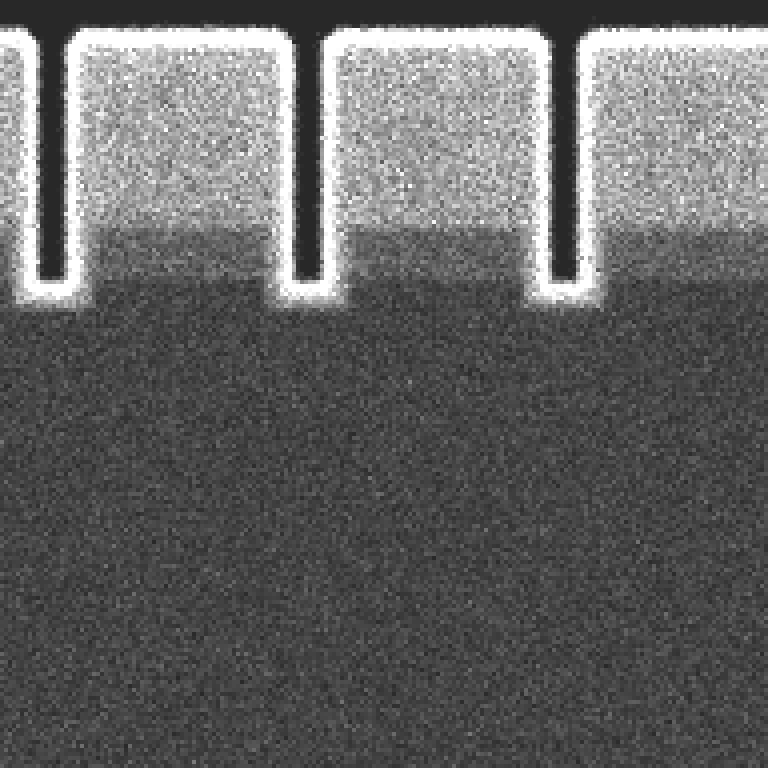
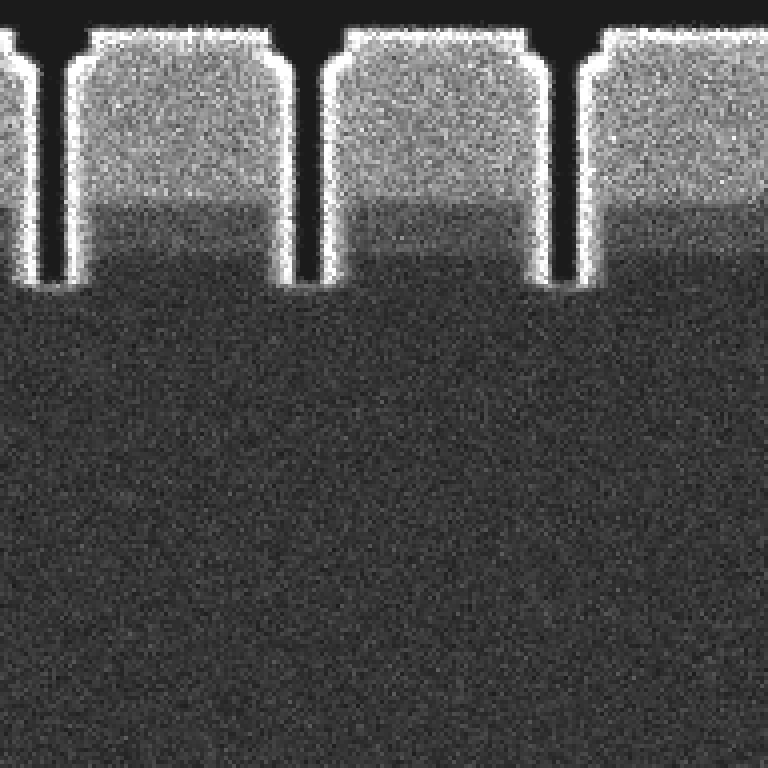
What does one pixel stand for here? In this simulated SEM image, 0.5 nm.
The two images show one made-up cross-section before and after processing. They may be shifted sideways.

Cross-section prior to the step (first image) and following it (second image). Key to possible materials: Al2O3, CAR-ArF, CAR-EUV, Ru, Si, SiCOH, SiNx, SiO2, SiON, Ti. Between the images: Al2O3 was removed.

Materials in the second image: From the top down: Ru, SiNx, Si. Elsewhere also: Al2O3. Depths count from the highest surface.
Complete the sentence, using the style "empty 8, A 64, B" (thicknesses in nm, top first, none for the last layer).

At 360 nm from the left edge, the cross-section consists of Ru 86, SiNx 26, Si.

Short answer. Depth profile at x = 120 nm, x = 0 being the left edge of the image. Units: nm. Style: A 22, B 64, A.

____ Ru 86, SiNx 26, Si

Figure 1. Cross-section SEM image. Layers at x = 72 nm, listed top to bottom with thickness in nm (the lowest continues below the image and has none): Ru 86, SiNx 26, Si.